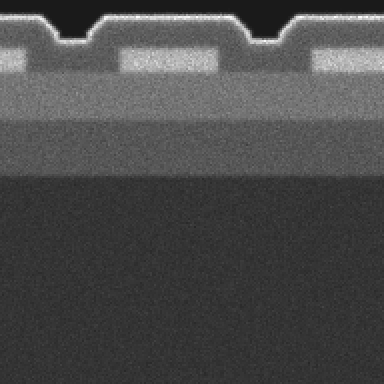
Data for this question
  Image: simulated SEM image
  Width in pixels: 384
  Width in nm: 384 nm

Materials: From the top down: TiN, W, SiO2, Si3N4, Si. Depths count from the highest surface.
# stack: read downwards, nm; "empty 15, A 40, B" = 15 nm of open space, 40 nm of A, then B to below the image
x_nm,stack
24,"TiN 32, W 24, SiO2 48, Si3N4 56, Si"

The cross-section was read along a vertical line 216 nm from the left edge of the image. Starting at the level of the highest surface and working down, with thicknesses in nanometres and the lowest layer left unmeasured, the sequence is TiN 32, W 24, SiO2 48, Si3N4 56, Si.